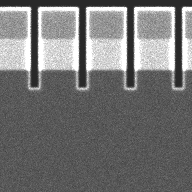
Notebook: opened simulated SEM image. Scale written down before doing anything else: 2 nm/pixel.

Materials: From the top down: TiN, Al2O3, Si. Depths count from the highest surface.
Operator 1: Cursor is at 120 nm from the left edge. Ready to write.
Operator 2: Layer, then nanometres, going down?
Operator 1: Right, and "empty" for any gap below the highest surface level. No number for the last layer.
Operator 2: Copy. TiN 62, Al2O3 62, Si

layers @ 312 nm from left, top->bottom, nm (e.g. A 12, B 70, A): TiN 62, Al2O3 62, Si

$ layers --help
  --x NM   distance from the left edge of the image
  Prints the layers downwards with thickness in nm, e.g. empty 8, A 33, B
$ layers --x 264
empty 160, Si